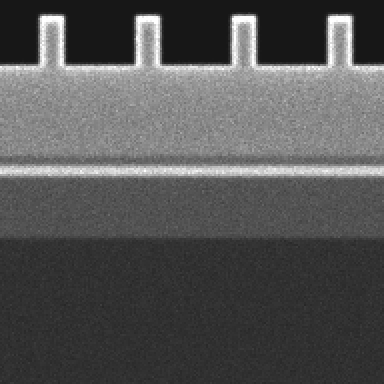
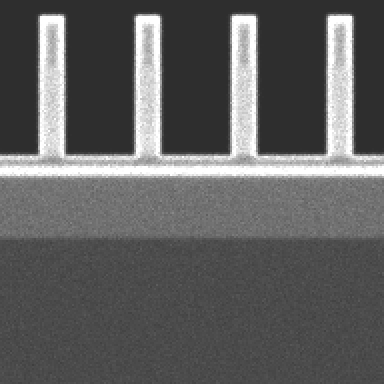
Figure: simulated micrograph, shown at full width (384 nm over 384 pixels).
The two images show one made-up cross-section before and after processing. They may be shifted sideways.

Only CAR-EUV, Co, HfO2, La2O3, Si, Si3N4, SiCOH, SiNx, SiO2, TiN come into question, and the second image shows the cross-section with Co removed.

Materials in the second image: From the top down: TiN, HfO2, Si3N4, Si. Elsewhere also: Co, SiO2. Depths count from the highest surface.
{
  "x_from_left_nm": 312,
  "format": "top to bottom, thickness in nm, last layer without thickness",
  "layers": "empty 140, TiN 10, HfO2 10, Si3N4 62, Si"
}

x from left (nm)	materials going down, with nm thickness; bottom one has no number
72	empty 140, TiN 10, HfO2 10, Si3N4 62, Si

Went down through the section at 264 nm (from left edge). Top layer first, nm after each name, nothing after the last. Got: empty 140, TiN 10, HfO2 10, Si3N4 62, Si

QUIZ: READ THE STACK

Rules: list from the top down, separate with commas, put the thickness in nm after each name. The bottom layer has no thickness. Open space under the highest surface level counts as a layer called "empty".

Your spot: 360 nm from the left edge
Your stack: empty 140, TiN 10, HfO2 10, Si3N4 62, Si